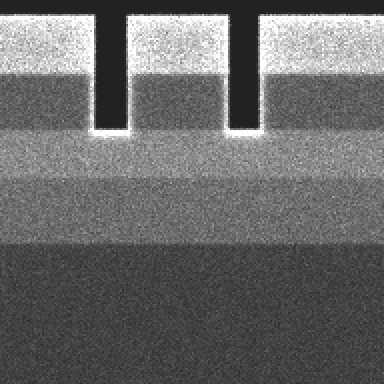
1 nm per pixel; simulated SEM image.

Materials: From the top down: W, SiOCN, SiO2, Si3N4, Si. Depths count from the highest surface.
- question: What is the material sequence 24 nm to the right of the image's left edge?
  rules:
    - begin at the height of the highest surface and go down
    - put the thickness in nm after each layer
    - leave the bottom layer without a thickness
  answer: W 58, SiOCN 56, SiO2 48, Si3N4 66, Si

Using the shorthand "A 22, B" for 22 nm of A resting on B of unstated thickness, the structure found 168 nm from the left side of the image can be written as W 58, SiOCN 56, SiO2 48, Si3N4 66, Si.